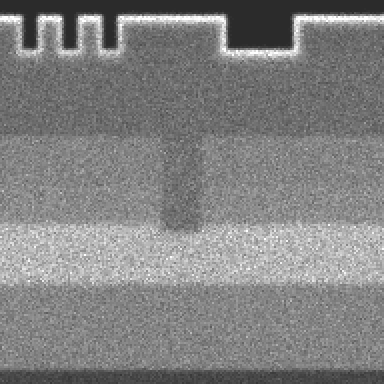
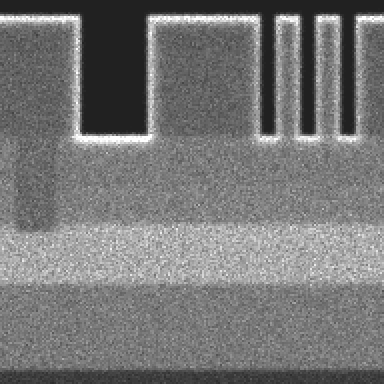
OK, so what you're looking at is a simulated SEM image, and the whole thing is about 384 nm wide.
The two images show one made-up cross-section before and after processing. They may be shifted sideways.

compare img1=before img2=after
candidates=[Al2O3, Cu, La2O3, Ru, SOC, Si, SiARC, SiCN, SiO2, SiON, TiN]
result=removed:SOC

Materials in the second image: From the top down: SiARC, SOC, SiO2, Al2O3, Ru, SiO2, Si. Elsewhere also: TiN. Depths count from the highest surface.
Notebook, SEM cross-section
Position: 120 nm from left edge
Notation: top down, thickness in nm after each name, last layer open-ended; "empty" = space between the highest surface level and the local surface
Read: empty 120, SiO2 50, Al2O3 38, Ru 60, SiO2 86, Si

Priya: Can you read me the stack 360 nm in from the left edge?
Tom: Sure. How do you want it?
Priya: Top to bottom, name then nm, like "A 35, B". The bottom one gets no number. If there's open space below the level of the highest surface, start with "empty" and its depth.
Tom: SiARC 34, SOC 86, SiO2 50, Al2O3 38, Ru 60, SiO2 86, Si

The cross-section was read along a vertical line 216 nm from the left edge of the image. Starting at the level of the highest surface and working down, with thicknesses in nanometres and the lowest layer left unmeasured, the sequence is SiARC 34, SOC 86, SiO2 50, Al2O3 38, Ru 60, SiO2 86, Si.